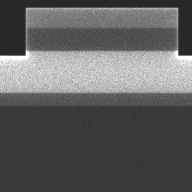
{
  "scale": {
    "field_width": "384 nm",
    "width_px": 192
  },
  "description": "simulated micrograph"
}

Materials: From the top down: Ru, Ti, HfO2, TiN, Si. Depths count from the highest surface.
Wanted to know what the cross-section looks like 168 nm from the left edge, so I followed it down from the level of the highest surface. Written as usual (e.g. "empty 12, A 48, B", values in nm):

Ru 40, Ti 46, HfO2 84, TiN 26, Si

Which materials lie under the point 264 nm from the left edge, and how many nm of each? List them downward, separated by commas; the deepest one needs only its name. Ru 40, Ti 46, HfO2 84, TiN 26, Si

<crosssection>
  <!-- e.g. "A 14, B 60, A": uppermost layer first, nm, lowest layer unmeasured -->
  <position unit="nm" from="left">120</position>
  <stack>Ru 40, Ti 46, HfO2 84, TiN 26, Si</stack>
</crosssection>